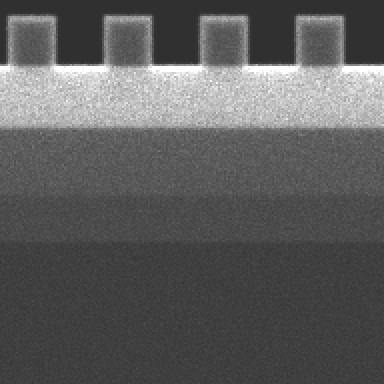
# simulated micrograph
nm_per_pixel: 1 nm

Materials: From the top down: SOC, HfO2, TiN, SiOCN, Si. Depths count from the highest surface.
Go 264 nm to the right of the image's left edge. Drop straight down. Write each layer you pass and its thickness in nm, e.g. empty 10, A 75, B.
empty 50, HfO2 62, TiN 68, SiOCN 46, Si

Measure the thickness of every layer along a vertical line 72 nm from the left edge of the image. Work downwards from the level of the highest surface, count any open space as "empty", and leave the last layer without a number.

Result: empty 50, HfO2 62, TiN 68, SiOCN 46, Si